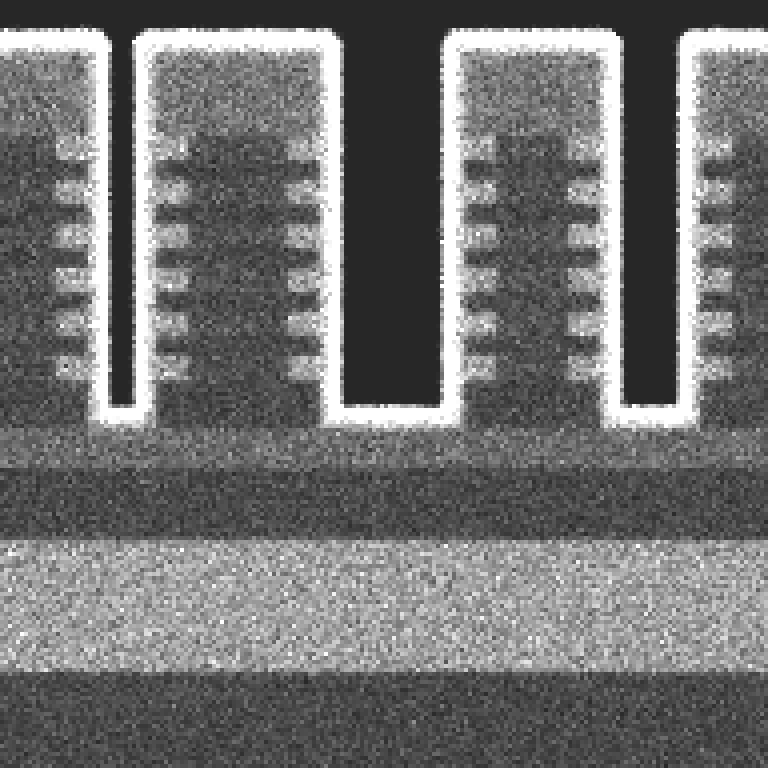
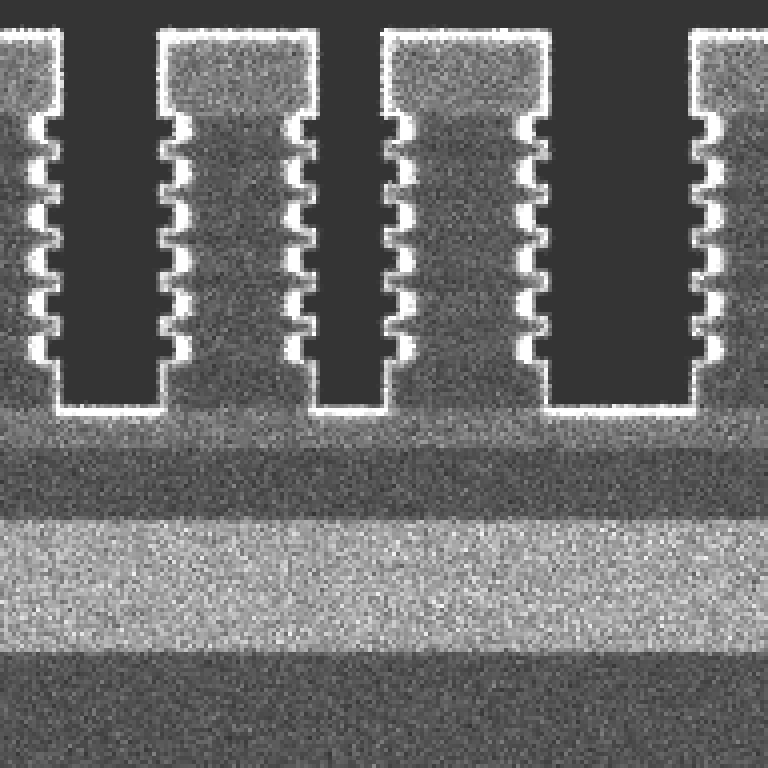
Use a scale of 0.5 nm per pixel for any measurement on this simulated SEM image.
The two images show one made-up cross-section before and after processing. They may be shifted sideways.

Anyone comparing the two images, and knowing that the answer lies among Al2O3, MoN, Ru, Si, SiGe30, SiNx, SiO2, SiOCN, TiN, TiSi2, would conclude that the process removed Al2O3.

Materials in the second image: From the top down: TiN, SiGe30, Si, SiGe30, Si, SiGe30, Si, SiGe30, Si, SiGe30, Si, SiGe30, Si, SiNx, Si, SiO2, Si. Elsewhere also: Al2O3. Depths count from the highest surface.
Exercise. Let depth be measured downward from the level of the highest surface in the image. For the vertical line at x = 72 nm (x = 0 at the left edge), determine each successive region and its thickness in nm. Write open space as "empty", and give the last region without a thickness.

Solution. empty 188, SiNx 20, Si 36, SiO2 66, Si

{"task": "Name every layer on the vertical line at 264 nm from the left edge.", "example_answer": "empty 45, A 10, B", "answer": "TiN 42, Al2O3 12, Si 10, Al2O3 12, Si 10, Al2O3 12, Si 10, Al2O3 12, Si 10, Al2O3 12, Si 10, Al2O3 12, Si 24, SiNx 20, Si 36, SiO2 66, Si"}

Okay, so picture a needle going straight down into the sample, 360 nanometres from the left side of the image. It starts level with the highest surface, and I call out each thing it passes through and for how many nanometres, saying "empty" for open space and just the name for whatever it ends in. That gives TiN 42, Al2O3 12, Si 10, Al2O3 12, Si 10, Al2O3 12, Si 10, Al2O3 12, Si 10, Al2O3 12, Si 10, Al2O3 12, Si 24, SiNx 20, Si 36, SiO2 66, Si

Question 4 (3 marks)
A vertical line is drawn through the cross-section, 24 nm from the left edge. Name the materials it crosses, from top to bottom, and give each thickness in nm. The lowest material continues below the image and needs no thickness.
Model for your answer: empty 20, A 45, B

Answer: TiN 42, empty 12, Si 10, empty 12, Si 10, empty 12, Si 10, empty 12, Si 10, empty 12, Si 10, empty 12, Si 24, SiNx 20, Si 36, SiO2 66, Si